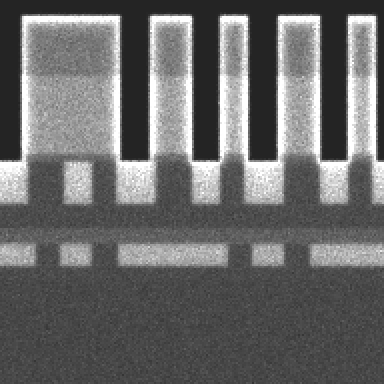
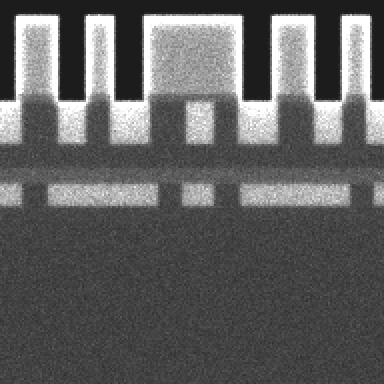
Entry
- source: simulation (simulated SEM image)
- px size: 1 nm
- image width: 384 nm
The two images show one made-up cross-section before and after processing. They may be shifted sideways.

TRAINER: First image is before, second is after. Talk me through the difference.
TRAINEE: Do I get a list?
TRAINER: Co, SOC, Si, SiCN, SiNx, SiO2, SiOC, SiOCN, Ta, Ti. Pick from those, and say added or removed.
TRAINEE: removed: SOC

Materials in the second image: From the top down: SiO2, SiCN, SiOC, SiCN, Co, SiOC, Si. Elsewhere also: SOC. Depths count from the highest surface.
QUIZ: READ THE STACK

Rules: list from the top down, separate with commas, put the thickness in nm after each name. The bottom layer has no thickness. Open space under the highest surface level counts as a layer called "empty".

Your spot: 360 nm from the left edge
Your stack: SiO2 78, SiCN 8, SiOC 66, SiCN 16, SiOC 36, Si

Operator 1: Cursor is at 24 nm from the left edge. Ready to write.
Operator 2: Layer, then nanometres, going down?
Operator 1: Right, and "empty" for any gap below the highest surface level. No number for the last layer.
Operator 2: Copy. SiO2 78, SiCN 8, SiOC 66, SiCN 16, SiOC 36, Si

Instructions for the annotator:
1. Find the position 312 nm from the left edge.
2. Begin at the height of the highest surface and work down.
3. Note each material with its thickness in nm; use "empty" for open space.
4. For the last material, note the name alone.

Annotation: SiO2 78, SiCN 8, SiOC 66, SiCN 16, Co 22, SiOC 14, Si